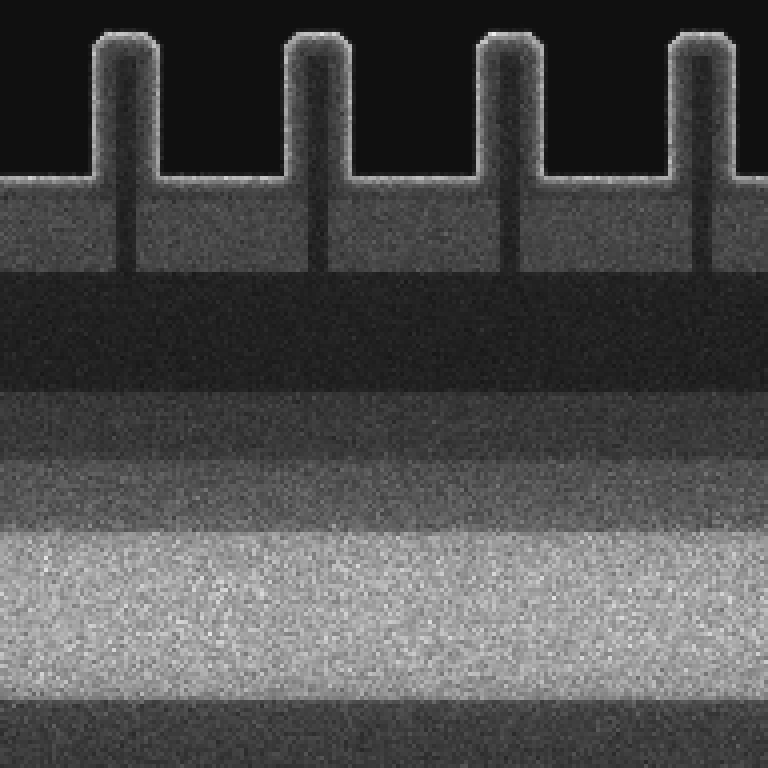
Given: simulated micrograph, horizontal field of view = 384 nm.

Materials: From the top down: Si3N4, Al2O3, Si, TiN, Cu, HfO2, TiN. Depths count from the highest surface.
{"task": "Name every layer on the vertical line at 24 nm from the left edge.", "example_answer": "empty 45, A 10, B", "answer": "empty 72, Si3N4 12, Al2O3 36, Si 60, TiN 34, Cu 36, HfO2 84, TiN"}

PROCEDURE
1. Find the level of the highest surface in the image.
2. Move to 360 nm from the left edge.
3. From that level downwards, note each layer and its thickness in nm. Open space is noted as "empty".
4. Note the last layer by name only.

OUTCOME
Si3N4 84, Al2O3 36, Si 60, TiN 34, Cu 36, HfO2 84, TiN